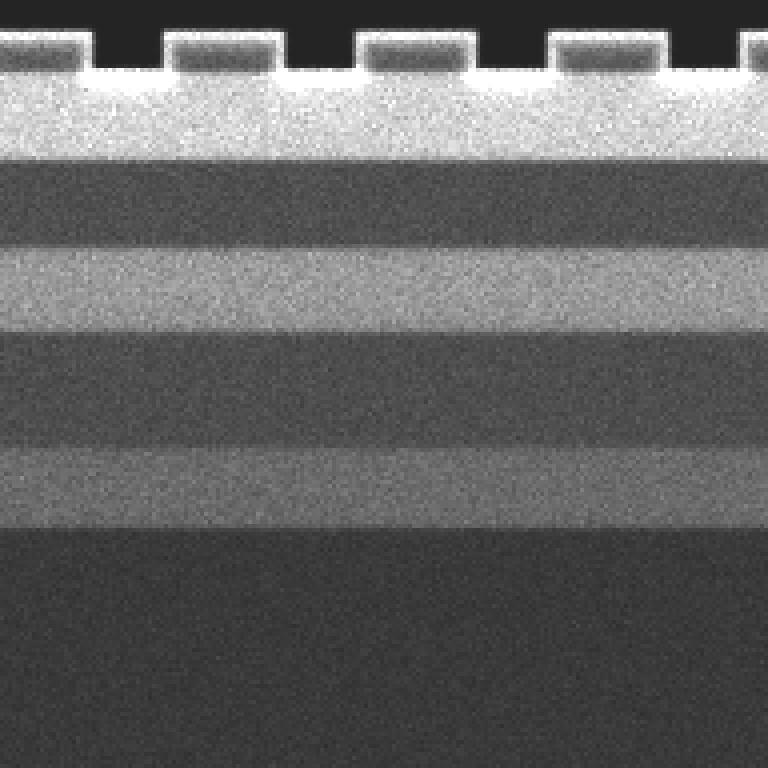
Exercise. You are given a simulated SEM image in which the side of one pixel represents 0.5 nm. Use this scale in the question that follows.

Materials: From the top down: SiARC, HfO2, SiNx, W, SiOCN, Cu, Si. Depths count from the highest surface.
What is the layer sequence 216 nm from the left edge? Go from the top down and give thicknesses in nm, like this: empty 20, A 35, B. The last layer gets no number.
SiARC 20, HfO2 44, SiNx 44, W 42, SiOCN 58, Cu 40, Si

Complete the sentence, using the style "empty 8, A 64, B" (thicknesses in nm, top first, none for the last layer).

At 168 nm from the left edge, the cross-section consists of empty 20, HfO2 44, SiNx 44, W 42, SiOCN 58, Cu 40, Si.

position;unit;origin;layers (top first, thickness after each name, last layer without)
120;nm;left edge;SiARC 20, HfO2 44, SiNx 44, W 42, SiOCN 58, Cu 40, Si